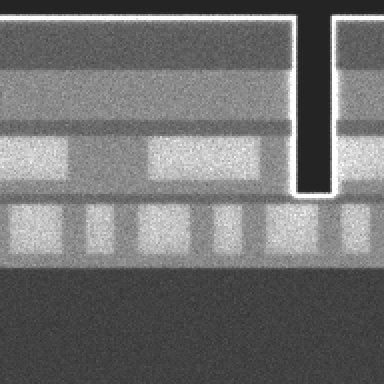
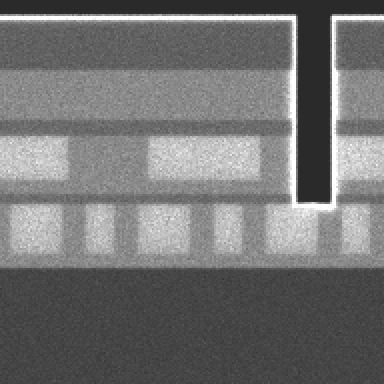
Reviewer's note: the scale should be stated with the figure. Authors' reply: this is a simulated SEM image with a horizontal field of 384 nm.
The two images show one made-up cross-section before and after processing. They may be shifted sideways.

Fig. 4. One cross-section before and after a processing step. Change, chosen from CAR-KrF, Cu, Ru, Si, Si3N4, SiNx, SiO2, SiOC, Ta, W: Si3N4 removed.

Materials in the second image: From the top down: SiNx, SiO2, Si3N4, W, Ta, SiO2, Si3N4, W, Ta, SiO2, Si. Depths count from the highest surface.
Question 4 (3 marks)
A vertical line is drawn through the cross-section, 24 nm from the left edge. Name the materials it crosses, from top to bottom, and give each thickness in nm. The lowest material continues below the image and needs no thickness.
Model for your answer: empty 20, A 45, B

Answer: SiNx 54, SiO2 50, Si3N4 16, W 34, Ta 10, SiO2 14, Si3N4 10, W 40, Ta 10, SiO2 14, Si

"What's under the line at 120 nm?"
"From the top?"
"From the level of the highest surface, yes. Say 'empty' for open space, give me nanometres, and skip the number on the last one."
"SiNx 54, SiO2 50, Si3N4 16, SiO2 58, Si3N4 10, SiO2 64, Si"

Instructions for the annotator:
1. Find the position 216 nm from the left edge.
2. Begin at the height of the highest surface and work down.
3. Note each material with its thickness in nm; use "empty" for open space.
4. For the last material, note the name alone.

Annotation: SiNx 54, SiO2 50, Si3N4 16, W 34, Ta 10, SiO2 14, Si3N4 10, Ta 50, SiO2 14, Si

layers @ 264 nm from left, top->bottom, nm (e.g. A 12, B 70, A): SiNx 54, SiO2 50, Si3N4 16, SiO2 58, Si3N4 10, SiO2 64, Si